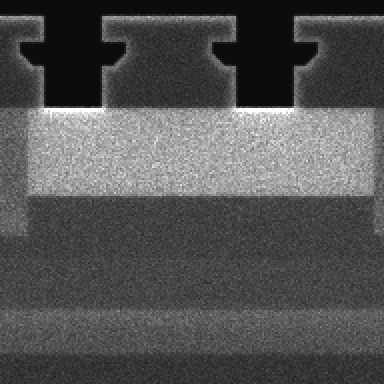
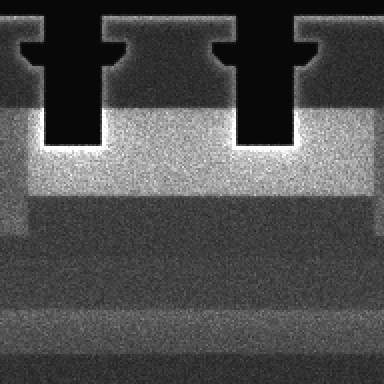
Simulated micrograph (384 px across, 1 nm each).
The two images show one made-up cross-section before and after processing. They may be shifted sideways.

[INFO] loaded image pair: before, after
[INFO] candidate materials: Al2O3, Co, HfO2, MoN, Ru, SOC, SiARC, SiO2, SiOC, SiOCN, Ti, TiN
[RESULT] removed HfO2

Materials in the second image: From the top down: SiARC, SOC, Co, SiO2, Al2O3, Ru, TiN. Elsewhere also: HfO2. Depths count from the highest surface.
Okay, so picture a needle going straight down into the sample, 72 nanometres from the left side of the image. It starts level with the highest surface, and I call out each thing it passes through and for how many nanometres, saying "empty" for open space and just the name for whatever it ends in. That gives empty 130, HfO2 50, SiO2 62, Al2O3 52, Ru 44, TiN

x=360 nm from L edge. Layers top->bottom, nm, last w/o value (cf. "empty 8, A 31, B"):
SiARC 26, SOC 66, HfO2 88, SiO2 62, Al2O3 52, Ru 44, TiN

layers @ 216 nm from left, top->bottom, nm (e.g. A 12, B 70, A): SiARC 26, empty 16, SOC 50, HfO2 88, SiO2 62, Al2O3 52, Ru 44, TiN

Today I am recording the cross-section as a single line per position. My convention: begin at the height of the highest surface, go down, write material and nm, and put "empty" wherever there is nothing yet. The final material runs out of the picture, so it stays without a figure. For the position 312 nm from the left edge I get SiARC 26, empty 16, SOC 50, HfO2 88, SiO2 62, Al2O3 52, Ru 44, TiN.